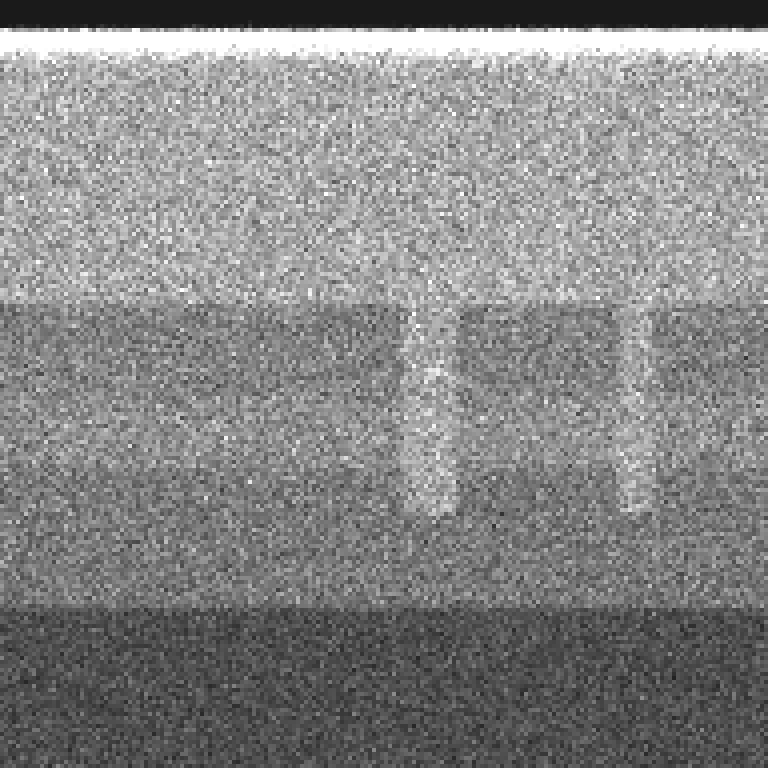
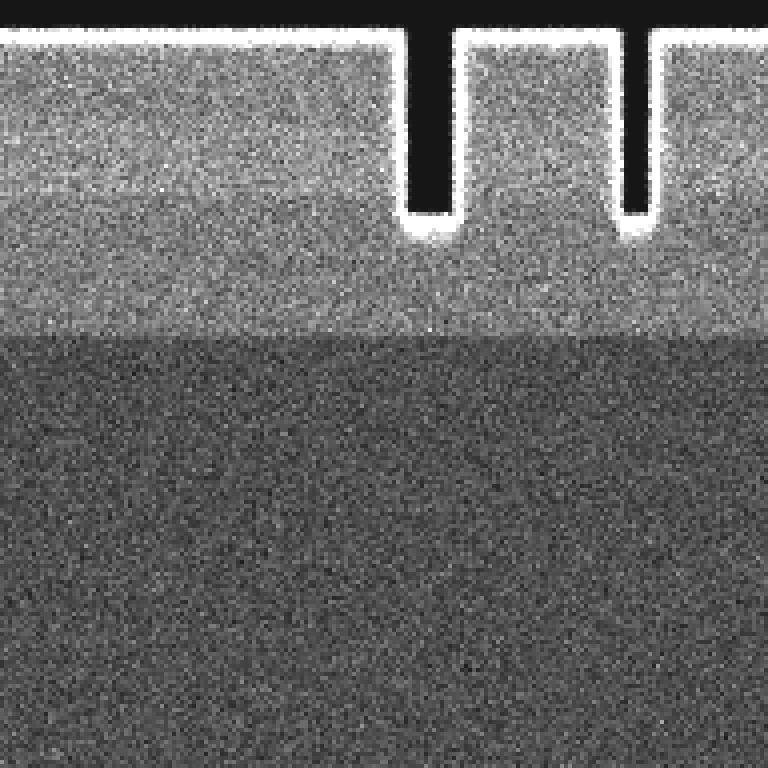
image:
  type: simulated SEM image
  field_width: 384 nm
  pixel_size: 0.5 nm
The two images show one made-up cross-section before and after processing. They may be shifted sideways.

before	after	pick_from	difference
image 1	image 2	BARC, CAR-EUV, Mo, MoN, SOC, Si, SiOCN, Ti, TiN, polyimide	SOC removed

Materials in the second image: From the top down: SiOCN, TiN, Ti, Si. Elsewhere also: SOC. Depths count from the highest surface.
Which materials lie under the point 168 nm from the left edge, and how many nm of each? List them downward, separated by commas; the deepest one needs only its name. SiOCN 46, TiN 36, Ti 70, Si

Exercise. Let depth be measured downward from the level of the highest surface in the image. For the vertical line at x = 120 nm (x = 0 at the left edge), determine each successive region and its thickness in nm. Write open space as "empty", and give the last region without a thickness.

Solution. SiOCN 46, TiN 36, Ti 70, Si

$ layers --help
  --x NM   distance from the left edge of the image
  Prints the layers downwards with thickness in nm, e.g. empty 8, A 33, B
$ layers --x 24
SiOCN 46, TiN 36, Ti 70, Si